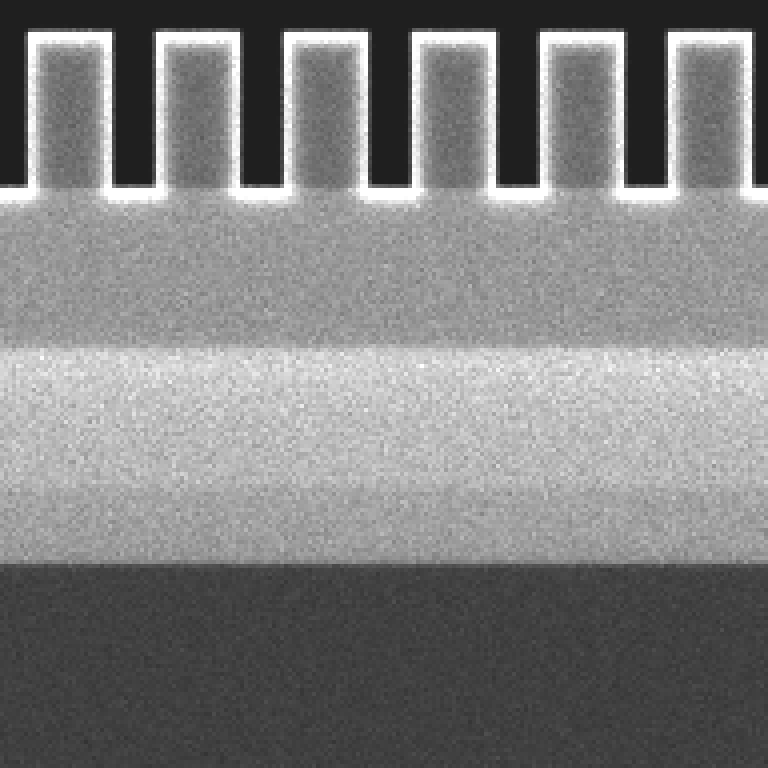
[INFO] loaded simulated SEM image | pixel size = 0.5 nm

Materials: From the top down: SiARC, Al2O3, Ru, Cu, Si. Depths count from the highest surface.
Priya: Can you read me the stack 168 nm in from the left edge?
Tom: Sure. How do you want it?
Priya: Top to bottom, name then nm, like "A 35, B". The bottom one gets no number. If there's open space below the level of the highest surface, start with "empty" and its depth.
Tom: SiARC 78, Al2O3 80, Ru 70, Cu 38, Si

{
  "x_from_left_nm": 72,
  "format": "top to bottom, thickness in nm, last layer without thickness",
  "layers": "empty 78, Al2O3 80, Ru 70, Cu 38, Si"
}